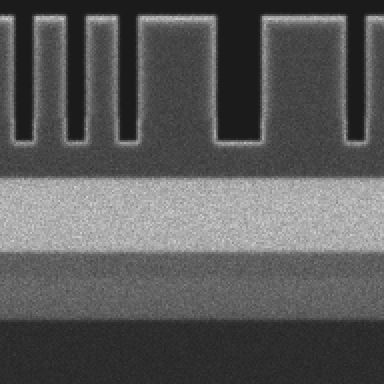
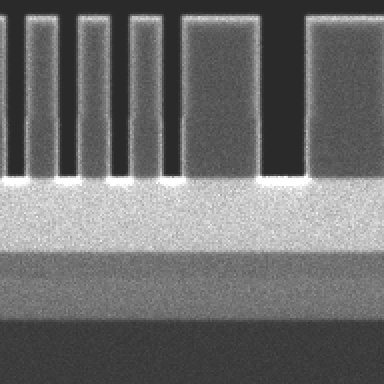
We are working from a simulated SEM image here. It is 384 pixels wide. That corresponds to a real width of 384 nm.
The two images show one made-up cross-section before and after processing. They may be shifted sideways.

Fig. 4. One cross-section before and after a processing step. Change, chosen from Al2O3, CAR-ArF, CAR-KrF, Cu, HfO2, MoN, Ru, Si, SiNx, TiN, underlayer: TiN removed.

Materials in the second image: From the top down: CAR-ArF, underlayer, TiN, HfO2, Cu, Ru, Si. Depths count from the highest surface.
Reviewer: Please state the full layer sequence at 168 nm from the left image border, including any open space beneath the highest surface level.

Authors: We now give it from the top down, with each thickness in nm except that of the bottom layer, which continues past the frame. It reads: empty 162, HfO2 74, Cu 26, Ru 42, Si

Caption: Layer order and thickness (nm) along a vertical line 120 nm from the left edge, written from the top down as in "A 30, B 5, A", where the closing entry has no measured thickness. empty 162, HfO2 74, Cu 26, Ru 42, Si